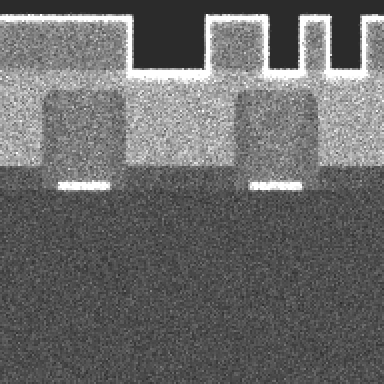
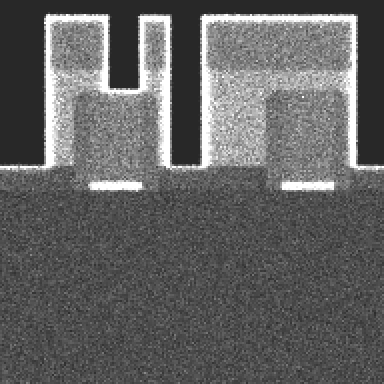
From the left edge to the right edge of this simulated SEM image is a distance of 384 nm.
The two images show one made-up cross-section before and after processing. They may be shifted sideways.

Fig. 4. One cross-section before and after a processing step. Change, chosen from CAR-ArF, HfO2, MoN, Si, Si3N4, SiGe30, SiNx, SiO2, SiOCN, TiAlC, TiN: SiO2 removed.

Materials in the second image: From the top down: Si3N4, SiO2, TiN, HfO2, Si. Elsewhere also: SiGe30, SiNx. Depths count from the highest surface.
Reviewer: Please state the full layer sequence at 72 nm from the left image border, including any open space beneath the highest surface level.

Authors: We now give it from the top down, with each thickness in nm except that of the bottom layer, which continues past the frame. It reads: Si3N4 54, SiO2 96, SiGe30 24, Si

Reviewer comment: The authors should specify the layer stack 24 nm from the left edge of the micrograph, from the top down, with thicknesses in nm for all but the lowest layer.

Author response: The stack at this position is empty 150, SiGe30 24, Si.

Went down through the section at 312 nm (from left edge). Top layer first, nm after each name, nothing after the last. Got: Si3N4 54, SiO2 20, TiN 92, HfO2 8, Si